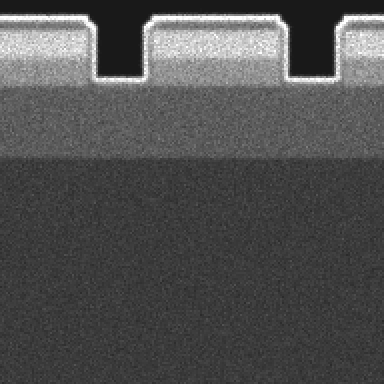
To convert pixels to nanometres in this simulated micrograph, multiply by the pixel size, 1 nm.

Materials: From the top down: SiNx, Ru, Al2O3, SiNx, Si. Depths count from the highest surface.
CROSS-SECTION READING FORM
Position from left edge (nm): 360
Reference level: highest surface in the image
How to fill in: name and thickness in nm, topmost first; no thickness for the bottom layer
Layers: SiNx 14, Ru 28, Al2O3 28, SiNx 72, Si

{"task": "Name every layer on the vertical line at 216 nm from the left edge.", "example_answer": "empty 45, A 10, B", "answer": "SiNx 14, Ru 28, Al2O3 28, SiNx 72, Si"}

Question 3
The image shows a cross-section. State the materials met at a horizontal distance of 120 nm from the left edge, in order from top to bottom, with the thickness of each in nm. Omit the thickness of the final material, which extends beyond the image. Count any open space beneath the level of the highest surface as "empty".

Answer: empty 62, SiNx 80, Si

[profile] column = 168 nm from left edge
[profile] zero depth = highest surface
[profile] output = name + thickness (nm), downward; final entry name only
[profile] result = SiNx 14, Ru 28, Al2O3 28, SiNx 72, Si